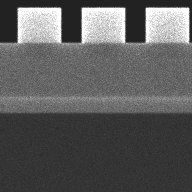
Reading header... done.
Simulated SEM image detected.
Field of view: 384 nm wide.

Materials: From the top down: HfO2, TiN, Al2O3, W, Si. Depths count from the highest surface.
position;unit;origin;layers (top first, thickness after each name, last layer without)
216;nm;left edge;HfO2 70, TiN 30, Al2O3 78, W 32, Si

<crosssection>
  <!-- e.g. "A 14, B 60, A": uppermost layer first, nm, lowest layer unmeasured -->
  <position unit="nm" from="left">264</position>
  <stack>empty 70, TiN 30, Al2O3 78, W 32, Si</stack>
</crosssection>